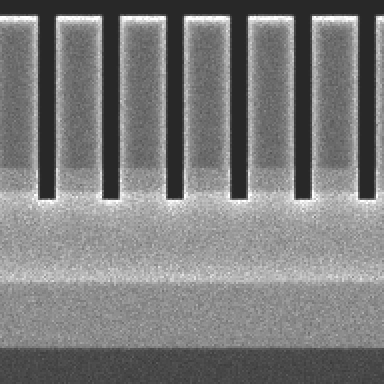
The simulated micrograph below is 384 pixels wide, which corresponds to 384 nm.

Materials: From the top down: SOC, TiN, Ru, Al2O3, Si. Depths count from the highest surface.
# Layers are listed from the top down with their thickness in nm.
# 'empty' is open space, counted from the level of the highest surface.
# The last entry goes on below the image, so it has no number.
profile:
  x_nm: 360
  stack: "empty 184, Ru 82, Al2O3 66, Si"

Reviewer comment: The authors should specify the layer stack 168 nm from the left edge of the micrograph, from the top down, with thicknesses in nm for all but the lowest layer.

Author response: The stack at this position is empty 184, Ru 82, Al2O3 66, Si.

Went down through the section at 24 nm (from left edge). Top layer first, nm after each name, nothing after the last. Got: SOC 152, TiN 24, Ru 90, Al2O3 66, Si